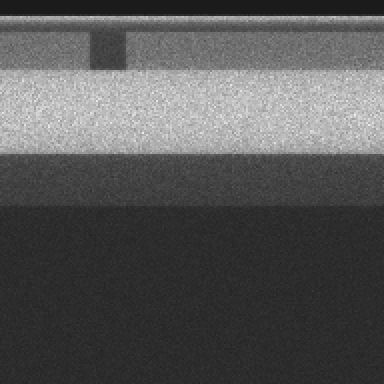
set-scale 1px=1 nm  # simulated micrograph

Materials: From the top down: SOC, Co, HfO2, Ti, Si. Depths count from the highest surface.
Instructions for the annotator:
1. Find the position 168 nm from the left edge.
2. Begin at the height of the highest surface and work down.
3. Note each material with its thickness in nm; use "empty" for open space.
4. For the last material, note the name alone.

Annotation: SOC 16, Co 38, HfO2 84, Ti 52, Si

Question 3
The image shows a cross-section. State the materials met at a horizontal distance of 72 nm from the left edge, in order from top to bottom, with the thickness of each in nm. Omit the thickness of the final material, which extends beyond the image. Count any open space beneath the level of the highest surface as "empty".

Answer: SOC 16, Co 38, HfO2 84, Ti 52, Si